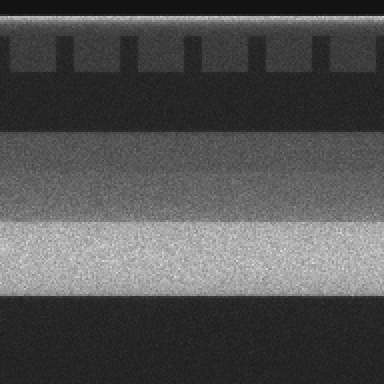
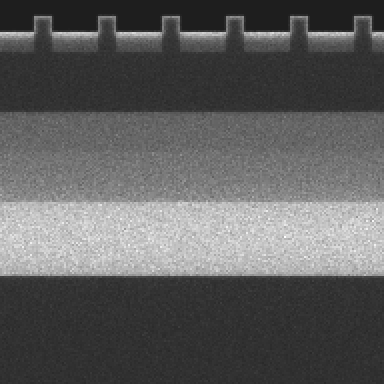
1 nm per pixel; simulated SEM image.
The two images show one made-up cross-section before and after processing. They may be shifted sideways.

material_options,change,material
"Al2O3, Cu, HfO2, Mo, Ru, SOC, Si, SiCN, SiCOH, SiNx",removed,SOC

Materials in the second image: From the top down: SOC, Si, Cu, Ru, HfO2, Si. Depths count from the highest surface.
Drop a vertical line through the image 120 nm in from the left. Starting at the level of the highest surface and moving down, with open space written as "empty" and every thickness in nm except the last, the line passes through empty 16, SOC 20, Si 60, Cu 40, Ru 50, HfO2 74, Si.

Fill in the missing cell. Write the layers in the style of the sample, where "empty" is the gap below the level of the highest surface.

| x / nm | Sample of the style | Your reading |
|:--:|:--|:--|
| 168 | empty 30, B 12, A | Si 96, Cu 40, Ru 50, HfO2 74, Si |